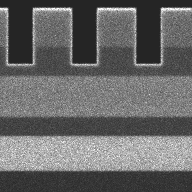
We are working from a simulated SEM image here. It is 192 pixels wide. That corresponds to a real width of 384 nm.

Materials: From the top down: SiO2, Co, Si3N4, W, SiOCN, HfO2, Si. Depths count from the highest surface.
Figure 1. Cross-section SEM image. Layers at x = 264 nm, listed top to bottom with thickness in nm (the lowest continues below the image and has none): SiO2 10, Co 68, Si3N4 58, W 82, SiOCN 38, HfO2 70, Si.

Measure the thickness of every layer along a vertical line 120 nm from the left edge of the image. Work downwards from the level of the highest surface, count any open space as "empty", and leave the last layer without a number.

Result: SiO2 10, Co 68, Si3N4 58, W 82, SiOCN 38, HfO2 70, Si